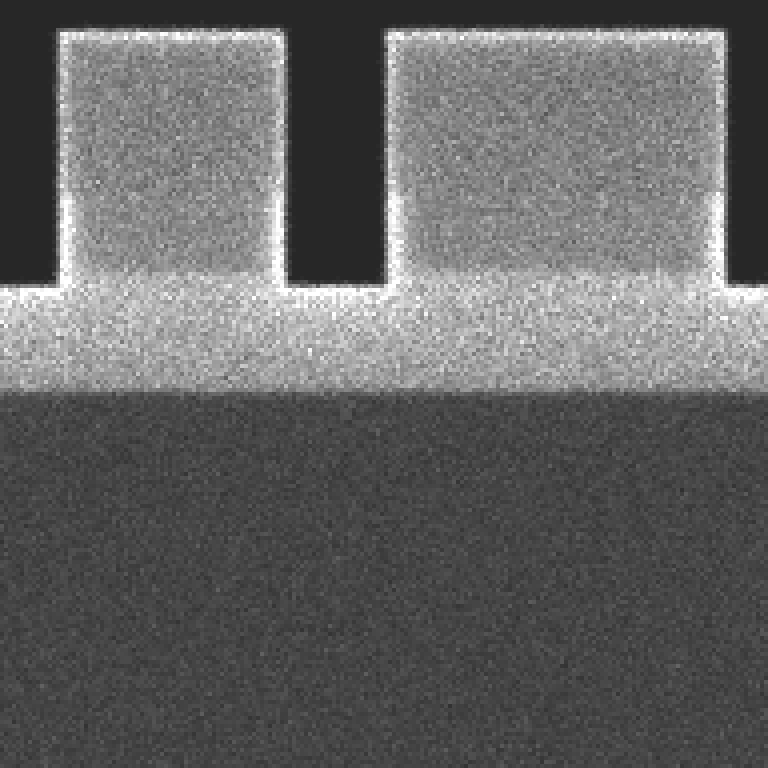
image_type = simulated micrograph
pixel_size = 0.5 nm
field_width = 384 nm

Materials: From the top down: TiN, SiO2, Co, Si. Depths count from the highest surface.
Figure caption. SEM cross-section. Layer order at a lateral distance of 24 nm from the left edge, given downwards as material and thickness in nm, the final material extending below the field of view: empty 128, Co 52, Si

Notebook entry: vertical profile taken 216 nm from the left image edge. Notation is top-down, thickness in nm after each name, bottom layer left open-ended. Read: TiN 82, SiO2 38, Co 60, Si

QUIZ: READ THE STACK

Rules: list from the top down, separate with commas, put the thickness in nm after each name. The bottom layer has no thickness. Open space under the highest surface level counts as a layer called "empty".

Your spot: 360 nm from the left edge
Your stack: TiN 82, SiO2 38, Co 60, Si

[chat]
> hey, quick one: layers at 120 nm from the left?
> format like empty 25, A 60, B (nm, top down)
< TiN 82, SiO2 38, Co 60, Si